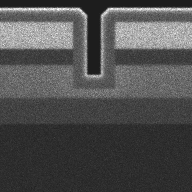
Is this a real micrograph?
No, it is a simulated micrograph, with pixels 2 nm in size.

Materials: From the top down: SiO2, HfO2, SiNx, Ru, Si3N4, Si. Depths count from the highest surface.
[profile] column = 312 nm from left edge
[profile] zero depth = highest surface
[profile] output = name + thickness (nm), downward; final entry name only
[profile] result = SiO2 28, HfO2 54, SiNx 32, Ru 66, Si3N4 52, Si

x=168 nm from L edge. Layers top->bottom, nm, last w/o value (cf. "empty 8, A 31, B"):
empty 10, SiO2 152, Ru 18, Si3N4 52, Si